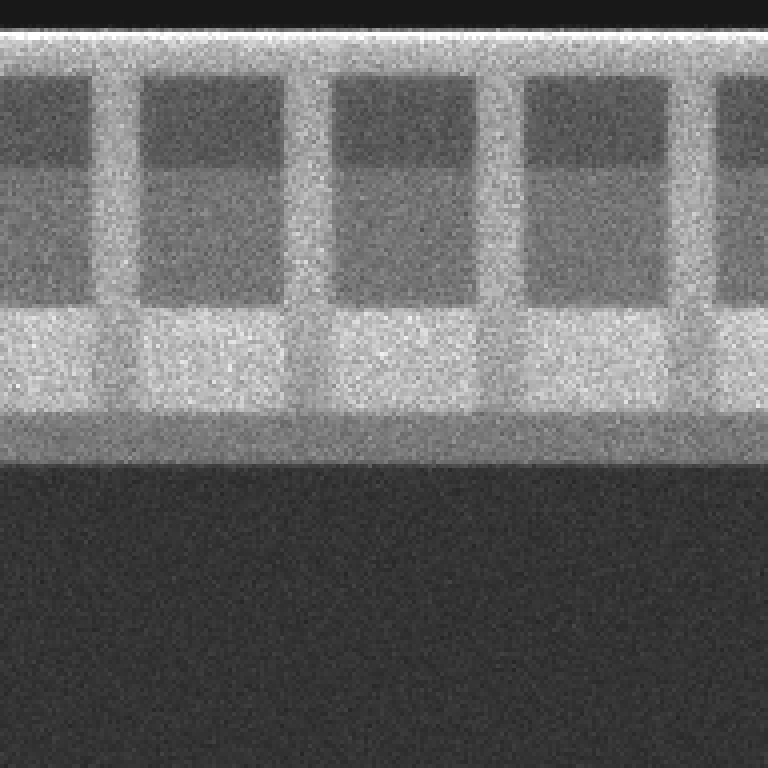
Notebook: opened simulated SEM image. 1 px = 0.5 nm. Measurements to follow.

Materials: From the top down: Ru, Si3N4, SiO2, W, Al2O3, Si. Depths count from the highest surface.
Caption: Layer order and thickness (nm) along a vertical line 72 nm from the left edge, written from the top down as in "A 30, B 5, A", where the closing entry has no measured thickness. Ru 22, Si3N4 46, SiO2 70, W 52, Al2O3 26, Si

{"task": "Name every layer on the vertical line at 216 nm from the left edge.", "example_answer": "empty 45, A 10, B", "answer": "Ru 22, Si3N4 46, SiO2 70, W 52, Al2O3 26, Si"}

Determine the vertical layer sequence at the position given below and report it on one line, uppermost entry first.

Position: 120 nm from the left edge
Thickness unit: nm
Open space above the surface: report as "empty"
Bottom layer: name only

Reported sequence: Ru 22, Si3N4 46, SiO2 70, W 52, Al2O3 26, Si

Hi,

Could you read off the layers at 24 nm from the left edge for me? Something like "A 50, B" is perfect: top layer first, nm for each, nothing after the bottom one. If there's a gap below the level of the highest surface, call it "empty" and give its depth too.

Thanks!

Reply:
Ru 22, Si3N4 46, SiO2 70, W 52, Al2O3 26, Si